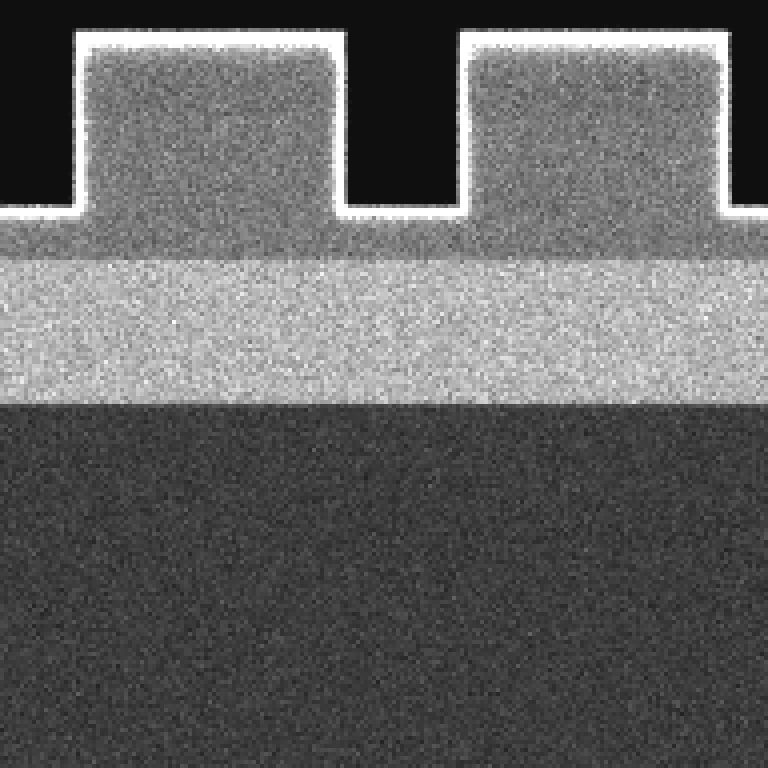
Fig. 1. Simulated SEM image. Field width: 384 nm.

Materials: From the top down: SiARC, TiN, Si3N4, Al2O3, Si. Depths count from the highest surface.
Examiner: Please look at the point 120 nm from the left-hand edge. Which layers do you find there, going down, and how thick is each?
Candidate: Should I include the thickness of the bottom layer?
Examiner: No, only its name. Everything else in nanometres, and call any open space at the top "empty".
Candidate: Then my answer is SiARC 14, TiN 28, Si3N4 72, Al2O3 72, Si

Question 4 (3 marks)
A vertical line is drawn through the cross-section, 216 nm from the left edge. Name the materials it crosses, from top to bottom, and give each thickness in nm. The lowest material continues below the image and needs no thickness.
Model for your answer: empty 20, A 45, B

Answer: empty 88, Si3N4 26, Al2O3 72, Si